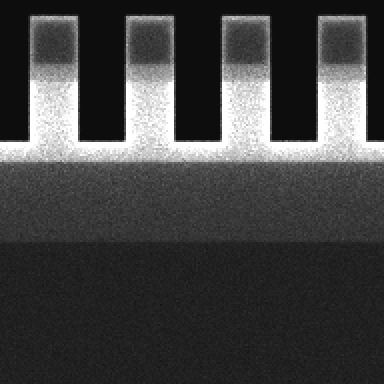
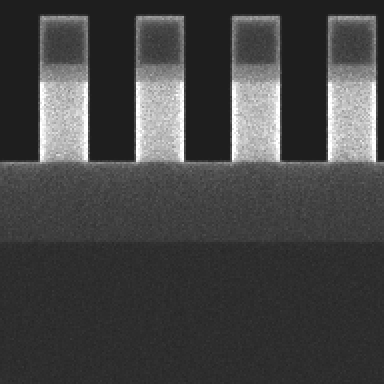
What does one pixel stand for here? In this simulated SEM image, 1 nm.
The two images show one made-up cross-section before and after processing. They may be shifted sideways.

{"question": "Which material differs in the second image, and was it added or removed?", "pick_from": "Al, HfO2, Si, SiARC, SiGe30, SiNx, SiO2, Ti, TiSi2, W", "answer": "HfO2, removed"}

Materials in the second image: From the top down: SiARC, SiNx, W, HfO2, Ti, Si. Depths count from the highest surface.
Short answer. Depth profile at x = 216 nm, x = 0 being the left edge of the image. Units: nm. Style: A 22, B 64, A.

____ empty 146, Ti 80, Si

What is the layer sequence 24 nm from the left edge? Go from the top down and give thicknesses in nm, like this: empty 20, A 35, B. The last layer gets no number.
empty 146, Ti 80, Si